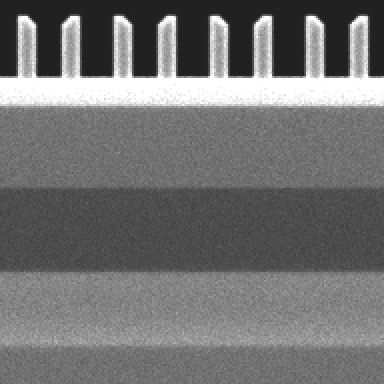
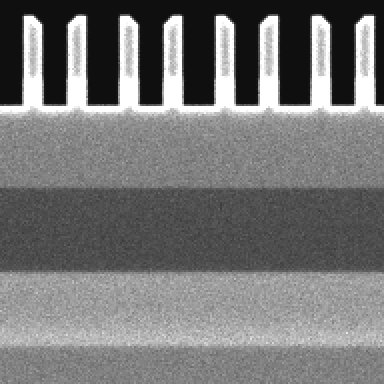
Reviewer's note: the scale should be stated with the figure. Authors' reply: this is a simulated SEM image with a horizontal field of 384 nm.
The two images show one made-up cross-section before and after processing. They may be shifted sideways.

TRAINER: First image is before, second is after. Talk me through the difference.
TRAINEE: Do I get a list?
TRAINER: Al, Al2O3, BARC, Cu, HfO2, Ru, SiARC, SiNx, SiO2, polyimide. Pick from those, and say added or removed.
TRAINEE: removed: HfO2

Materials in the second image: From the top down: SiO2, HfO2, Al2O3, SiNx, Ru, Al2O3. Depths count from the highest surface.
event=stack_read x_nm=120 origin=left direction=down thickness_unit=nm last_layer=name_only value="SiO2 62, HfO2 28, Al2O3 82, SiNx 84, Ru 74, Al2O3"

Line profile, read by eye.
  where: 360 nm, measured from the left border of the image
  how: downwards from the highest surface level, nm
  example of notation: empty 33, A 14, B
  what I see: empty 4, SiO2 58, HfO2 28, Al2O3 82, SiNx 84, Ru 74, Al2O3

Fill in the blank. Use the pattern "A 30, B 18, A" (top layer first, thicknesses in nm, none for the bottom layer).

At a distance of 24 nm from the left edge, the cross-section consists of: SiO2 62, HfO2 28, Al2O3 82, SiNx 84, Ru 74, Al2O3